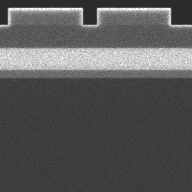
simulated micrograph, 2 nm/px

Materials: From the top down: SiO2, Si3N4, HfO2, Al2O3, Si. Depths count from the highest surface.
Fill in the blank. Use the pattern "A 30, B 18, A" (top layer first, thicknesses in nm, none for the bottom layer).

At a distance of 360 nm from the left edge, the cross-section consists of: empty 34, Si3N4 46, HfO2 44, Al2O3 16, Si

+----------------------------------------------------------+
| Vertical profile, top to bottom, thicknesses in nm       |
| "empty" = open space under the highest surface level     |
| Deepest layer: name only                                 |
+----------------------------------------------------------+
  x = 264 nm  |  SiO2 34, Si3N4 46, HfO2 44, Al2O3 16, Si